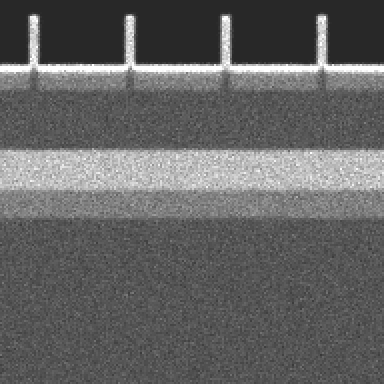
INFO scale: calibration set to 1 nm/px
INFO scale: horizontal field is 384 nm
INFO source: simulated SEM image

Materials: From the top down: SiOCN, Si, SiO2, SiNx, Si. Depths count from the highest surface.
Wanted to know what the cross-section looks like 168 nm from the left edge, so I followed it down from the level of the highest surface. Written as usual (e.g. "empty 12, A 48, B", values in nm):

empty 50, SiOCN 24, Si 60, SiO2 40, SiNx 28, Si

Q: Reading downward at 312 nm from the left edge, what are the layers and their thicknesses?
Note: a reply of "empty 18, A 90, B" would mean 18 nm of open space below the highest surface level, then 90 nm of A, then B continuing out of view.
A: empty 50, SiOCN 24, Si 60, SiO2 40, SiNx 28, Si